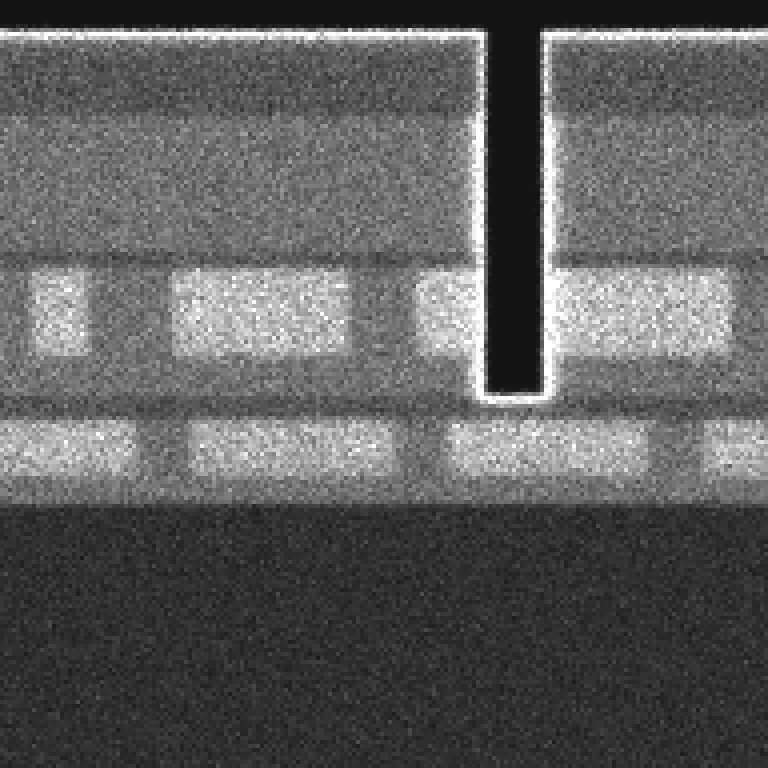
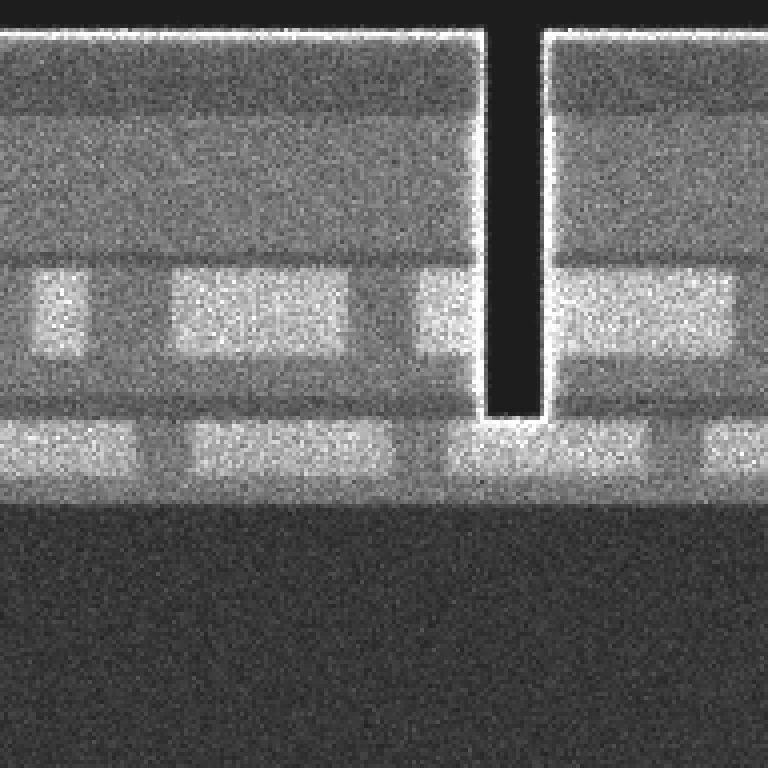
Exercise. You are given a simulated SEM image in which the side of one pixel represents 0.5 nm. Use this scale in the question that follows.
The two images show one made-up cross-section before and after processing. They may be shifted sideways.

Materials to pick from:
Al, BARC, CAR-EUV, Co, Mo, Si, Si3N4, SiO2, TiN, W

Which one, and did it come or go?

Si3N4 - removed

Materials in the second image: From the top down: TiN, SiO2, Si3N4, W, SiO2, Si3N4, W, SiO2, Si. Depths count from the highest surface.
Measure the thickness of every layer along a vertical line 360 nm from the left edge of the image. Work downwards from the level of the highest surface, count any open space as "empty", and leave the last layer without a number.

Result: TiN 42, SiO2 68, Si3N4 8, W 44, SiO2 20, Si3N4 12, W 28, SiO2 14, Si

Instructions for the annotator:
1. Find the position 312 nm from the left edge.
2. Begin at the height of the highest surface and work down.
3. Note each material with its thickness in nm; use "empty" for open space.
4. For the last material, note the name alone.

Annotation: TiN 42, SiO2 68, Si3N4 8, W 44, SiO2 20, Si3N4 12, W 28, SiO2 14, Si